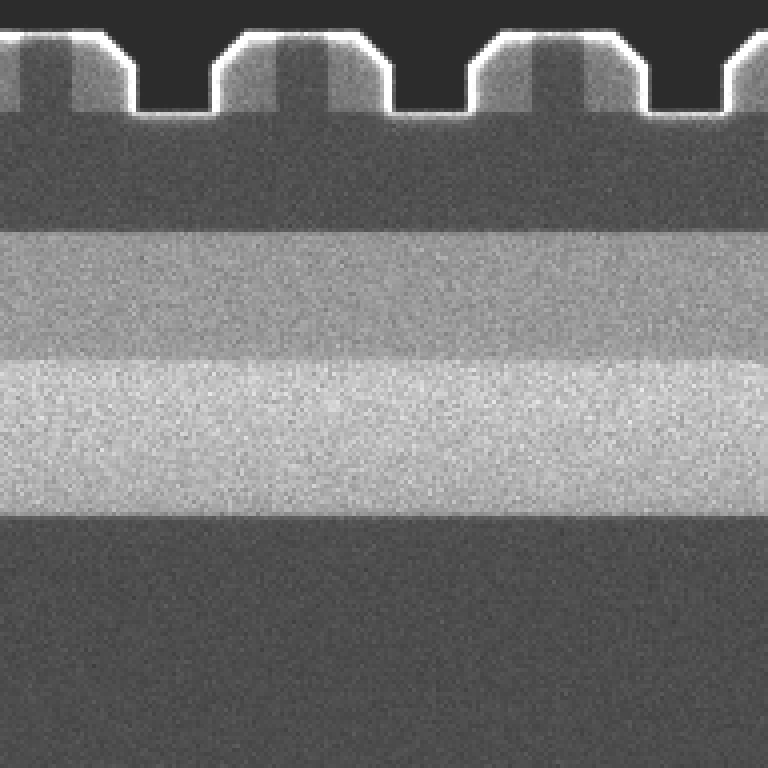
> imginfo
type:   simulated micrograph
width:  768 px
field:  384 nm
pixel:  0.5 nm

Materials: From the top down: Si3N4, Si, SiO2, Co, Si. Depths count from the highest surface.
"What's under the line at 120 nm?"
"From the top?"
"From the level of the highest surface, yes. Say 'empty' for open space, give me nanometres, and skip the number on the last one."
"empty 2, Si3N4 38, Si 60, SiO2 64, Co 78, Si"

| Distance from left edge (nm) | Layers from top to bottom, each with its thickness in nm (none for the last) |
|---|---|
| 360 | empty 40, Si 60, SiO2 64, Co 78, Si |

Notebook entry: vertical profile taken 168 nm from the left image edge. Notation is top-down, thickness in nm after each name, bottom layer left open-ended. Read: Si3N4 40, Si 60, SiO2 64, Co 78, Si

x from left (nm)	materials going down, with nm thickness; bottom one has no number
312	empty 6, Si3N4 34, Si 60, SiO2 64, Co 78, Si